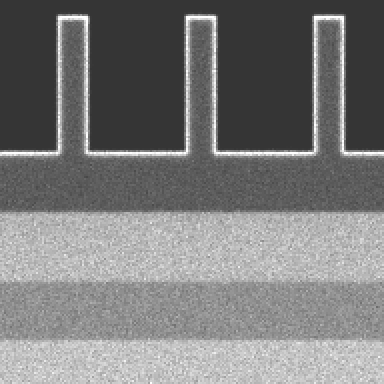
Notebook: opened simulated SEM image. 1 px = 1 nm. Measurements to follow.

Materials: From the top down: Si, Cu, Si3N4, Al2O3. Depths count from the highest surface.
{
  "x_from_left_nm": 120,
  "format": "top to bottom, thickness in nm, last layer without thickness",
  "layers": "empty 136, Si 60, Cu 70, Si3N4 58, Al2O3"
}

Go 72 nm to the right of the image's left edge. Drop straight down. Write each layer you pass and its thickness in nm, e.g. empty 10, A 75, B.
Si 196, Cu 70, Si3N4 58, Al2O3